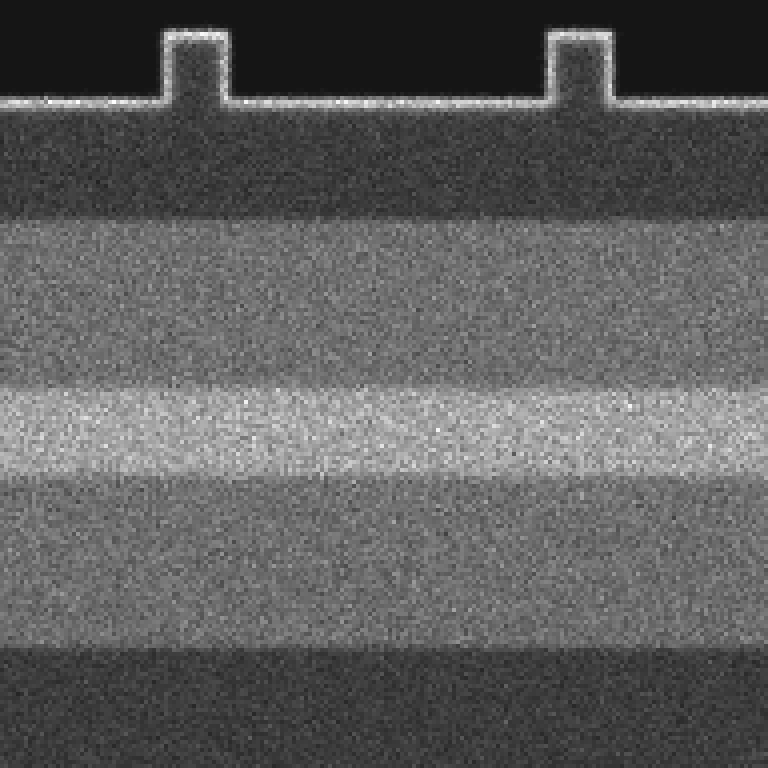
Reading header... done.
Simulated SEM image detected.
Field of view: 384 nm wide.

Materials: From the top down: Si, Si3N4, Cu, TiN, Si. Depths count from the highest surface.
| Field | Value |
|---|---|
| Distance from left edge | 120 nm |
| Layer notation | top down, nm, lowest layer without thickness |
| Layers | empty 34, Si 60, Si3N4 84, Cu 44, TiN 86, Si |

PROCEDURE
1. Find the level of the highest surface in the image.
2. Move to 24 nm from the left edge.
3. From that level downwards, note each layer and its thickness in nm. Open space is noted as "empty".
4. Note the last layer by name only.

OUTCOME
empty 34, Si 60, Si3N4 84, Cu 44, TiN 86, Si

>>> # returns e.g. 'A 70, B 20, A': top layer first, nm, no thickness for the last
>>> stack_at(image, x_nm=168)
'empty 34, Si 60, Si3N4 84, Cu 44, TiN 86, Si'